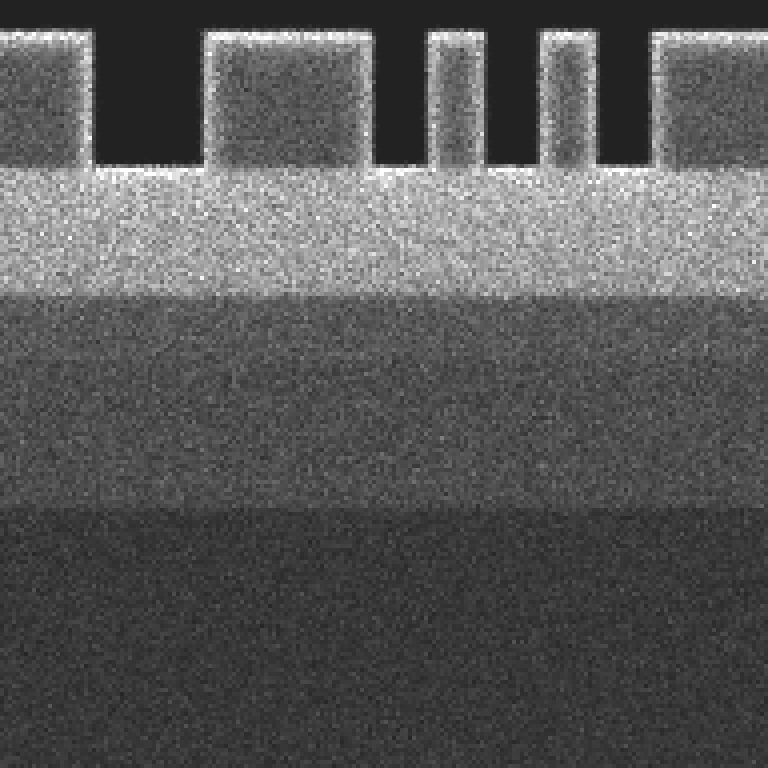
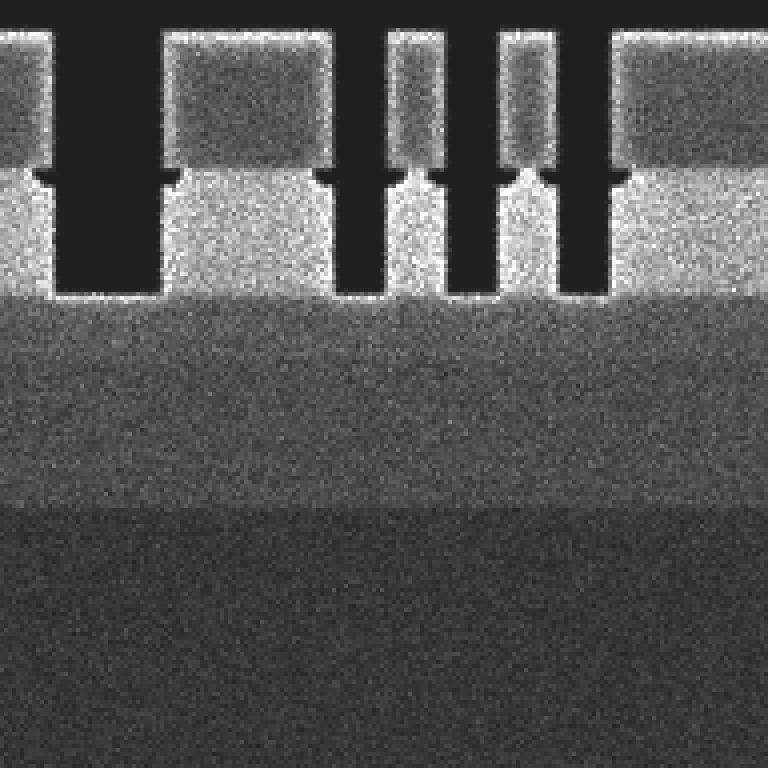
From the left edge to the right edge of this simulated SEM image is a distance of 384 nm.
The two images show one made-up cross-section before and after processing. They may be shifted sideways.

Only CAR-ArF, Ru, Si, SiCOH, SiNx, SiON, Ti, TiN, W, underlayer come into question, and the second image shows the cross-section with W removed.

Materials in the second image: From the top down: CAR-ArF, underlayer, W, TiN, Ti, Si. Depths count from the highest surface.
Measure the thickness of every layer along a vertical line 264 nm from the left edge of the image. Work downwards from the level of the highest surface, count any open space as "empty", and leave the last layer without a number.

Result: CAR-ArF 50, underlayer 18, W 64, TiN 32, Ti 74, Si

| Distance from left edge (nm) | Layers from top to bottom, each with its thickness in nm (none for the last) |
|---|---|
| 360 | CAR-ArF 50, underlayer 18, W 64, TiN 32, Ti 74, Si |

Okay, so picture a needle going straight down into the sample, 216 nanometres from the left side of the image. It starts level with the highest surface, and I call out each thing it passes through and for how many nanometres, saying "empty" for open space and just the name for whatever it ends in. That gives CAR-ArF 50, underlayer 18, empty 10, W 54, TiN 32, Ti 74, Si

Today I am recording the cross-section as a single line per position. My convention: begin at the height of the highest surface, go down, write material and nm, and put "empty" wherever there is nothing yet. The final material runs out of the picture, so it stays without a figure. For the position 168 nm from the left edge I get empty 132, TiN 32, Ti 74, Si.